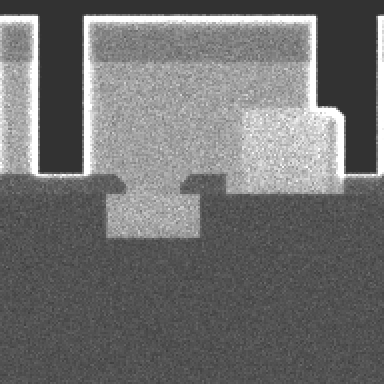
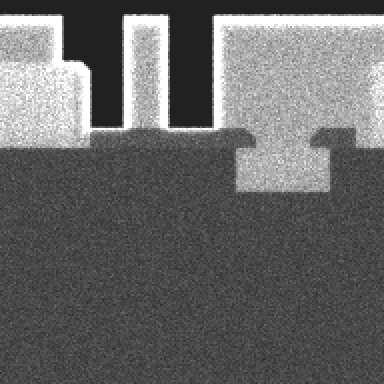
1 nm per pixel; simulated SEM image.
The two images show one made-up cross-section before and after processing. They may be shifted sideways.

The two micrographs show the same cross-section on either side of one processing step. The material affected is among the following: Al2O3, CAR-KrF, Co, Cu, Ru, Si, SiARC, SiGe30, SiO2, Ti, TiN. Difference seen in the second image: SiARC removed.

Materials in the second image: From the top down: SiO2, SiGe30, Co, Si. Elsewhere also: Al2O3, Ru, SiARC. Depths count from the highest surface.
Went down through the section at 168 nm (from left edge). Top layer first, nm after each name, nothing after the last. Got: empty 112, SiGe30 20, Si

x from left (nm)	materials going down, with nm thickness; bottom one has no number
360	SiO2 50, Al2O3 82, Si